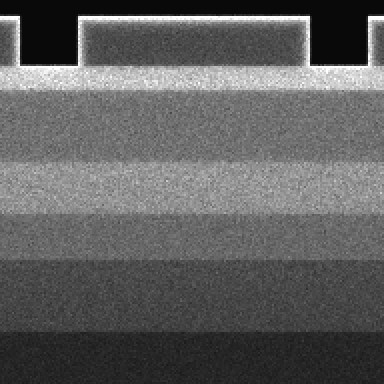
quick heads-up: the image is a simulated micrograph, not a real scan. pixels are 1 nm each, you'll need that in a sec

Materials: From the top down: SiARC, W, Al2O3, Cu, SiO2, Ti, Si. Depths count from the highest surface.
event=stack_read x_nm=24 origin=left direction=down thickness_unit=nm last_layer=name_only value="empty 50, W 24, Al2O3 72, Cu 52, SiO2 46, Ti 72, Si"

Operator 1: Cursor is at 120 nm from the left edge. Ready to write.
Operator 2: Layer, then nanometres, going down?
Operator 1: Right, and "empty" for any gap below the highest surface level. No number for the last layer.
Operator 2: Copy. SiARC 50, W 24, Al2O3 72, Cu 52, SiO2 46, Ti 72, Si